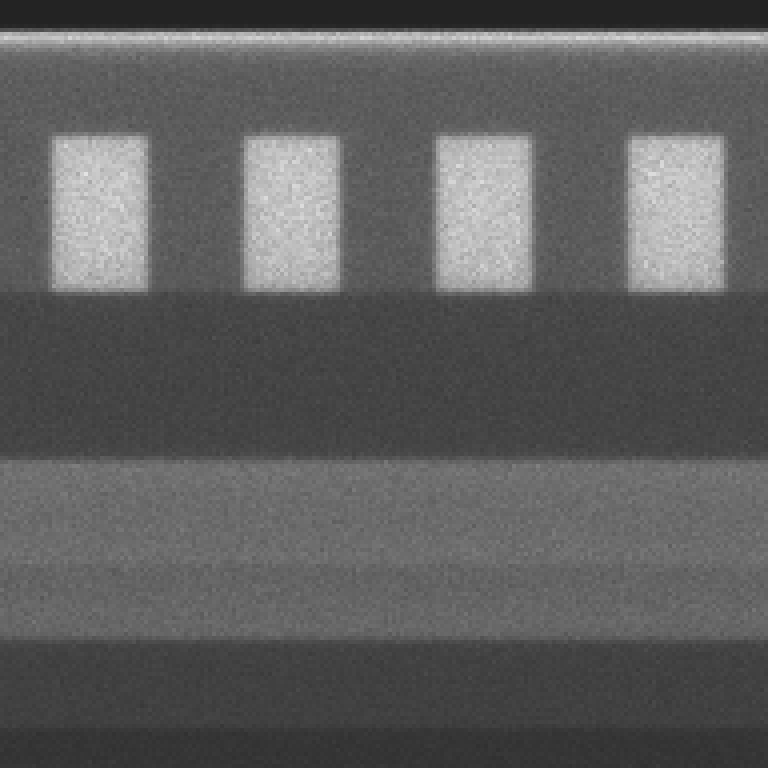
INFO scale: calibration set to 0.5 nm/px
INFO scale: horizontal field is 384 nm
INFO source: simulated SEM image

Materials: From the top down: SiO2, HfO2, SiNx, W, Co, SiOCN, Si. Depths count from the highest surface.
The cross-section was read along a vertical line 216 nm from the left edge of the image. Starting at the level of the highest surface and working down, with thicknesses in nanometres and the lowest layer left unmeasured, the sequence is SiO2 130, SiNx 84, W 52, Co 38, SiOCN 44, Si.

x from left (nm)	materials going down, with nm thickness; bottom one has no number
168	SiO2 52, HfO2 78, SiNx 84, W 52, Co 38, SiOCN 44, Si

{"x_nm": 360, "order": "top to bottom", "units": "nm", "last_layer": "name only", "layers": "SiO2 52, HfO2 78, SiNx 84, W 52, Co 38, SiOCN 44, Si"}